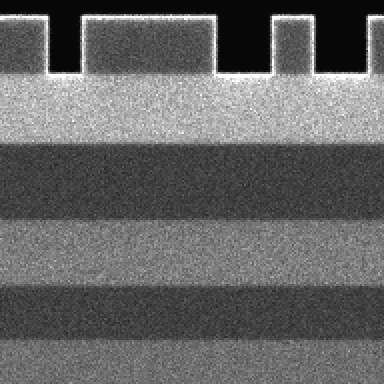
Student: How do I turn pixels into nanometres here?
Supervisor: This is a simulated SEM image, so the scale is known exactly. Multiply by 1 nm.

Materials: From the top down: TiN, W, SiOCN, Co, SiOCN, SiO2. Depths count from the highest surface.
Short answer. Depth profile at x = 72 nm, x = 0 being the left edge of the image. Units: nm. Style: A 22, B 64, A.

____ empty 58, W 70, SiOCN 76, Co 66, SiOCN 54, SiO2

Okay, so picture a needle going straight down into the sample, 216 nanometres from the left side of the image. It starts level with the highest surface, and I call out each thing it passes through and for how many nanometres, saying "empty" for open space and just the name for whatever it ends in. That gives empty 58, W 70, SiOCN 76, Co 66, SiOCN 54, SiO2